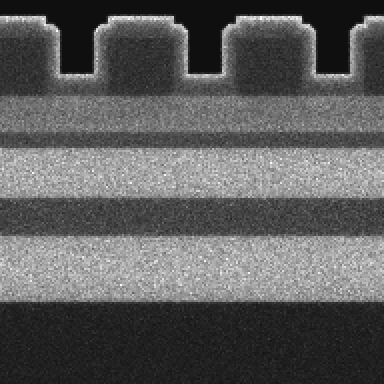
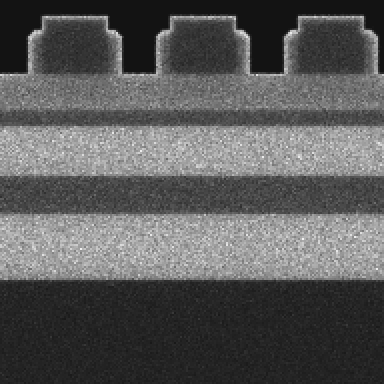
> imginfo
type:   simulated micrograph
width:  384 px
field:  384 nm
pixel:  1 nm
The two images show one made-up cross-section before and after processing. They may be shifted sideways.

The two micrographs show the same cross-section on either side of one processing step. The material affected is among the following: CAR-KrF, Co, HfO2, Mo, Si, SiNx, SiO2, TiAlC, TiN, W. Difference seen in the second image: SiO2 removed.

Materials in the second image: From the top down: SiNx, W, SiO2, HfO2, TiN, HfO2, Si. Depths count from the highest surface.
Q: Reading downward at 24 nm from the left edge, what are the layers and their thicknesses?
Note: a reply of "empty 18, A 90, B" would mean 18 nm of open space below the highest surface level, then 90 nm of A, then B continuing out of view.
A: empty 58, W 36, SiO2 16, HfO2 50, TiN 38, HfO2 66, Si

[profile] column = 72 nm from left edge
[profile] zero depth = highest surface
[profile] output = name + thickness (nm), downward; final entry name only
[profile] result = SiNx 58, W 36, SiO2 16, HfO2 50, TiN 38, HfO2 66, Si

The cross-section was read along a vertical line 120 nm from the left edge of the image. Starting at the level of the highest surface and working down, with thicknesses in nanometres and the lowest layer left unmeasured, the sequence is empty 20, SiO2 38, W 36, SiO2 16, HfO2 50, TiN 38, HfO2 66, Si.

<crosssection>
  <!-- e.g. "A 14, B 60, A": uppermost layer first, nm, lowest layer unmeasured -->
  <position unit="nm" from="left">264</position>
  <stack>empty 58, W 36, SiO2 16, HfO2 50, TiN 38, HfO2 66, Si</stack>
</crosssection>